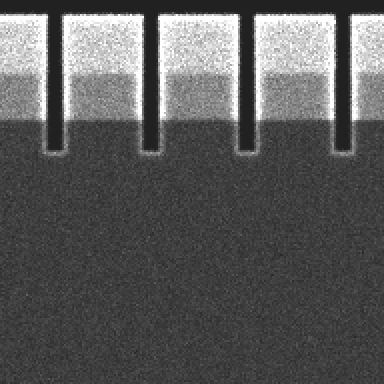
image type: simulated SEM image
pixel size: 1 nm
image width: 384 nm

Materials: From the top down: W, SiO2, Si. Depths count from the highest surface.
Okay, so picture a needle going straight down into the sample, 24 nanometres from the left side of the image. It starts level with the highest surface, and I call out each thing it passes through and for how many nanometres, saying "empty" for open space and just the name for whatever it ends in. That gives W 58, SiO2 46, Si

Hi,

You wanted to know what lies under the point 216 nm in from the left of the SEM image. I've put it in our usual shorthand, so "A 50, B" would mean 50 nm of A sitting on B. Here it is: W 58, SiO2 46, Si